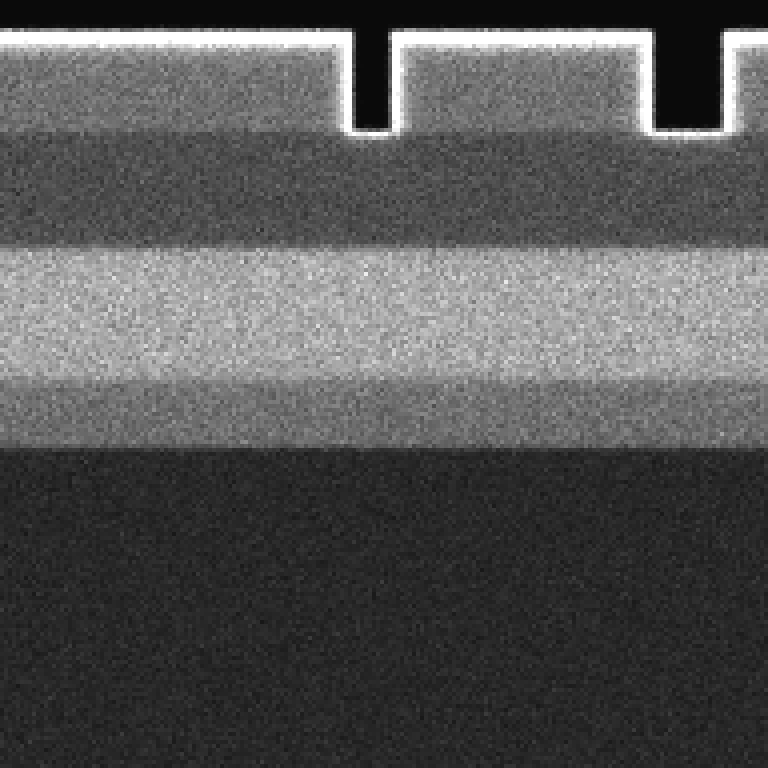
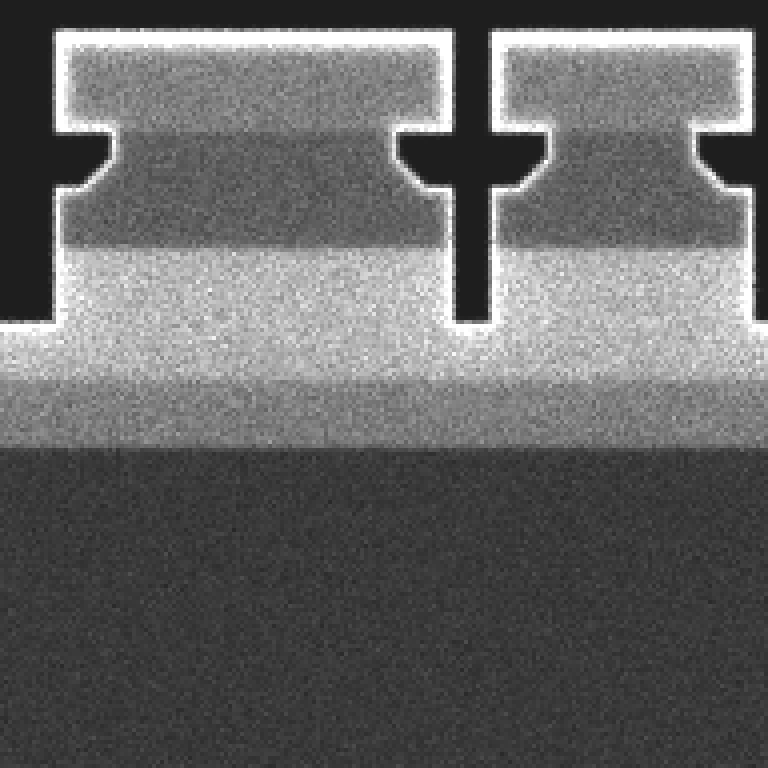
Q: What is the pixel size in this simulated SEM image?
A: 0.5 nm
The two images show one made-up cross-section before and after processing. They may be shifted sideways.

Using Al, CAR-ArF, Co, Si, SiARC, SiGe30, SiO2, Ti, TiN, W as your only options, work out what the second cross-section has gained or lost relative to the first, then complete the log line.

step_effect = removed TiN and W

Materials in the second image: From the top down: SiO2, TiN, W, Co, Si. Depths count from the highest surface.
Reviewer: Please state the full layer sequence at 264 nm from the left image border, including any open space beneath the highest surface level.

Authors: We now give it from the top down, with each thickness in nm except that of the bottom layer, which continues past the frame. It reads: SiO2 50, empty 22, TiN 36, W 66, Co 34, Si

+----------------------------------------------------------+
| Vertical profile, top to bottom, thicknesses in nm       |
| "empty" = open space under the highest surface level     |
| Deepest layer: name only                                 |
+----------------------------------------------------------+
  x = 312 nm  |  SiO2 50, TiN 58, W 66, Co 34, Si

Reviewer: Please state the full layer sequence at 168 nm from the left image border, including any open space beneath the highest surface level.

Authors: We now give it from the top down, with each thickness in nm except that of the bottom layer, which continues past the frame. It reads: SiO2 50, TiN 58, W 66, Co 34, Si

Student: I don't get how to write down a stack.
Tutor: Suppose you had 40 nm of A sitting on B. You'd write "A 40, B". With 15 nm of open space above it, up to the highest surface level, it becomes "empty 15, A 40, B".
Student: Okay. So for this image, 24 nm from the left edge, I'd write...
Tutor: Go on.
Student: empty 146, W 28, Co 34, Si